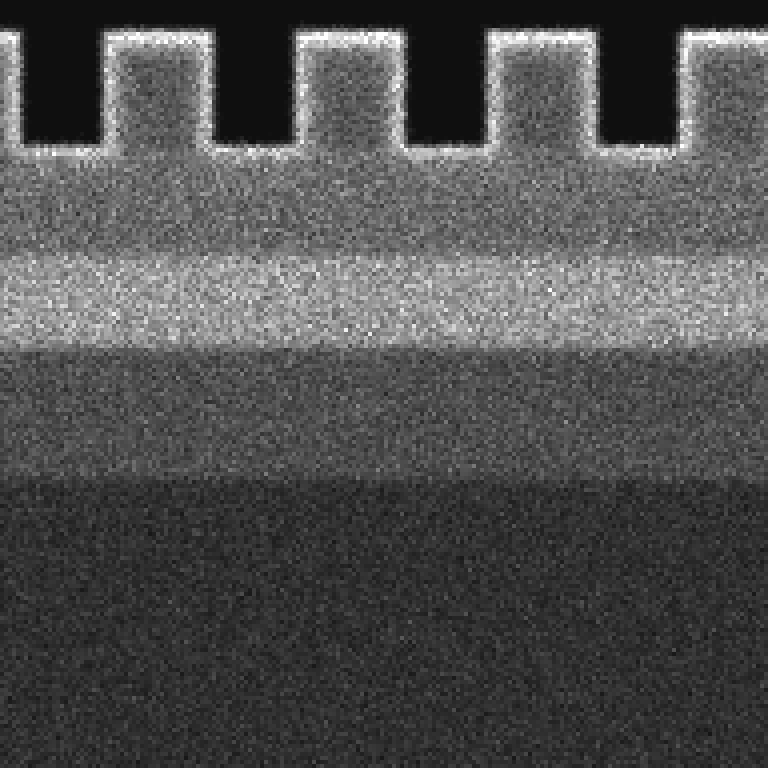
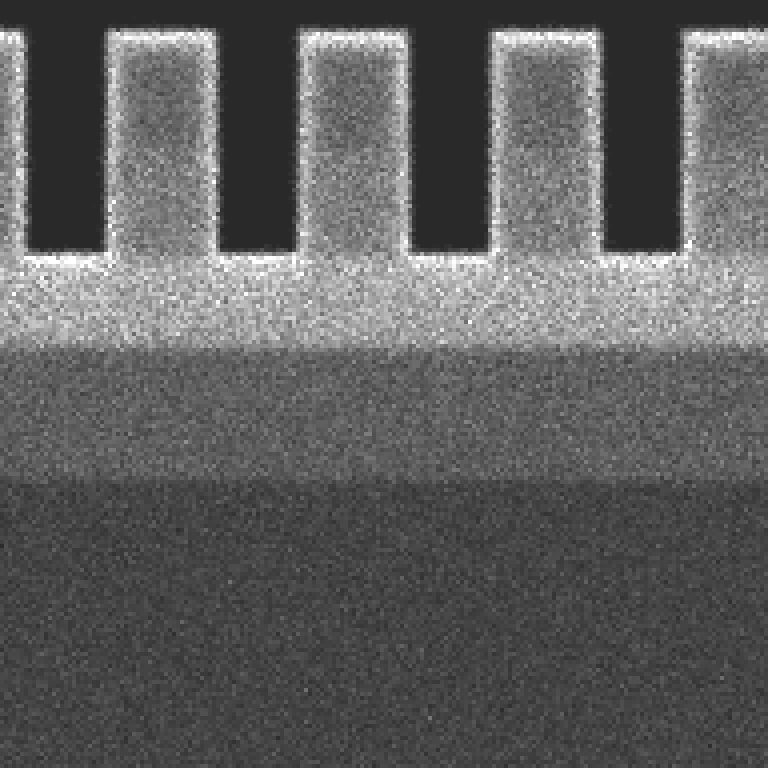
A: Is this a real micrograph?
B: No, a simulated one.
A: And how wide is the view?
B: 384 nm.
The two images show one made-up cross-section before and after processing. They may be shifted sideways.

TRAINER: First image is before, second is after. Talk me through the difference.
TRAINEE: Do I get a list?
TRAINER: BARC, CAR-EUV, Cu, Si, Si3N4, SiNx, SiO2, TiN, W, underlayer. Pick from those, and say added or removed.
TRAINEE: removed: TiN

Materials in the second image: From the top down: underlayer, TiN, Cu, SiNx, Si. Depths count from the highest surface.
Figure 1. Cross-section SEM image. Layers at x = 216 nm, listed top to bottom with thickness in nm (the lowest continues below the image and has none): empty 112, Cu 46, SiNx 66, Si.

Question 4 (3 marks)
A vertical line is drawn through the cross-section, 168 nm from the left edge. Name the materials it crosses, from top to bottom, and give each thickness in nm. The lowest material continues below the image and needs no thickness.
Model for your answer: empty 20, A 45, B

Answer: underlayer 58, TiN 54, Cu 46, SiNx 66, Si